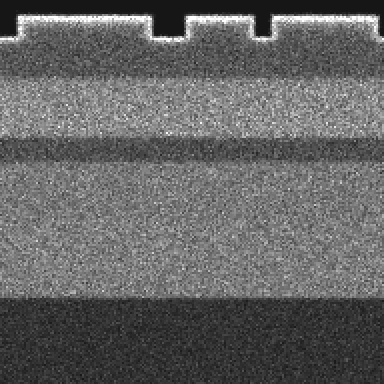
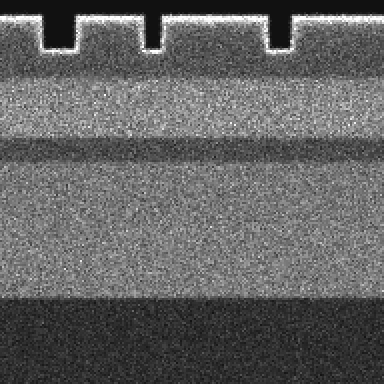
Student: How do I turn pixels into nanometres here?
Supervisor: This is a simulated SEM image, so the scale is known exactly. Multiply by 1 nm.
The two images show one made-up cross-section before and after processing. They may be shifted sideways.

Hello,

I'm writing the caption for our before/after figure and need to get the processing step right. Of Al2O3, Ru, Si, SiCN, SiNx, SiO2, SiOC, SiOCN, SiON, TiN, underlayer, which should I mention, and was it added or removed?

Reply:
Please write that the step removed TiN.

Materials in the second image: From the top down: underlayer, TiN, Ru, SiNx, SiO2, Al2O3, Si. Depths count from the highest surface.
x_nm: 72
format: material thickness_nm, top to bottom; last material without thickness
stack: empty 34, TiN 28, Ru 60, SiNx 24, SiO2 58, Al2O3 78, Si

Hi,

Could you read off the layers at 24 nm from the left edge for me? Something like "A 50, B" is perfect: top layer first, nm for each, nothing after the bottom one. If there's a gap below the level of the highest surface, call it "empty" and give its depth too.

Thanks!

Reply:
underlayer 22, TiN 40, Ru 60, SiNx 24, SiO2 58, Al2O3 78, Si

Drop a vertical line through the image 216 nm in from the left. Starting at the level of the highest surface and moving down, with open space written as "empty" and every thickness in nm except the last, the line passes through underlayer 22, TiN 40, Ru 60, SiNx 24, SiO2 58, Al2O3 78, Si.